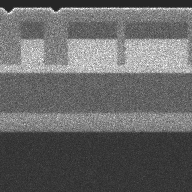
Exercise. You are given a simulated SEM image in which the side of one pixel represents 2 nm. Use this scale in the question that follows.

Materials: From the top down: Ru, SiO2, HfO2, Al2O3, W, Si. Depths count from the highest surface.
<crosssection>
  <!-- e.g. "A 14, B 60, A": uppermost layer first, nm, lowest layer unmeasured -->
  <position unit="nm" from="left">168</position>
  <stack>Ru 28, SiO2 34, HfO2 68, Al2O3 80, W 38, Si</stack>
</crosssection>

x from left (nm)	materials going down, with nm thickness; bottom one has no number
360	Ru 28, SiO2 34, HfO2 68, Al2O3 80, W 38, Si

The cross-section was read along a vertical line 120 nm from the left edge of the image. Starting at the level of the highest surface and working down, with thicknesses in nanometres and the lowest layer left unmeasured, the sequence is empty 2, Ru 112, HfO2 16, Al2O3 80, W 38, Si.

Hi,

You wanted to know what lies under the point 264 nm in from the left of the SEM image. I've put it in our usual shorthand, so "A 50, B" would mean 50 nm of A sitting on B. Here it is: Ru 28, SiO2 34, HfO2 68, Al2O3 80, W 38, Si